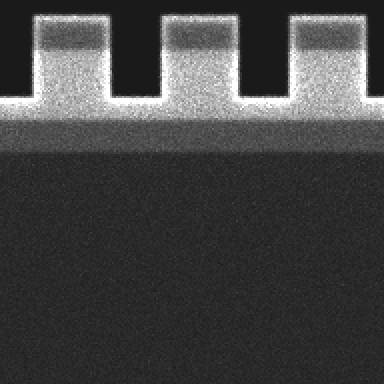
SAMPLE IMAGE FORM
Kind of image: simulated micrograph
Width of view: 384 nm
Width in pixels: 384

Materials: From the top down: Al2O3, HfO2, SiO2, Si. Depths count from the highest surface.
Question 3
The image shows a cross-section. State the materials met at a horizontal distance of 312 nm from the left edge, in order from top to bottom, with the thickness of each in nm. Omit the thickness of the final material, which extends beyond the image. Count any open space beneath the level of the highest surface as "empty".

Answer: Al2O3 34, HfO2 70, SiO2 32, Si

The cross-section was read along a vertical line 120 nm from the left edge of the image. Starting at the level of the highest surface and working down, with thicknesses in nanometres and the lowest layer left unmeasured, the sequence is empty 82, HfO2 22, SiO2 32, Si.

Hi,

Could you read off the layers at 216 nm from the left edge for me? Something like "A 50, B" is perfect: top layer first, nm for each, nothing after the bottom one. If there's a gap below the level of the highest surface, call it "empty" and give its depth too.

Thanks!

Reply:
Al2O3 34, HfO2 70, SiO2 32, Si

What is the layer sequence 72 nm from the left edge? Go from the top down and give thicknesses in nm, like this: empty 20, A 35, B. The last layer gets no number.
Al2O3 34, HfO2 70, SiO2 32, Si